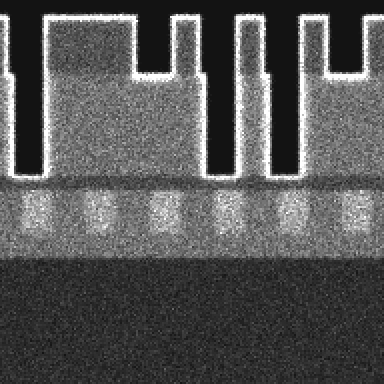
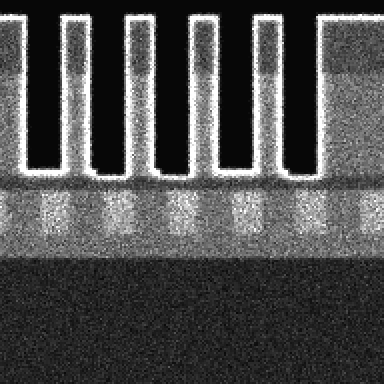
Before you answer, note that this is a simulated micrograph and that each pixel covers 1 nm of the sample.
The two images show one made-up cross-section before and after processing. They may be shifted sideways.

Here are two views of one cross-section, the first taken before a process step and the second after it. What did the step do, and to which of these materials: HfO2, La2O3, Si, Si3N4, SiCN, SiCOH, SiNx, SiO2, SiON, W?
It removed SiO2.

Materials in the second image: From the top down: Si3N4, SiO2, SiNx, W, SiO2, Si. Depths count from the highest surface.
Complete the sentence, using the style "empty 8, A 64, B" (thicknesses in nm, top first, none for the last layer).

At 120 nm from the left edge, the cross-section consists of empty 160, SiNx 14, W 44, SiO2 24, Si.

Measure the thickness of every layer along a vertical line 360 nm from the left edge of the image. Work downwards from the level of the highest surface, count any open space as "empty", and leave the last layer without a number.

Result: Si3N4 58, SiO2 102, SiNx 14, W 44, SiO2 24, Si